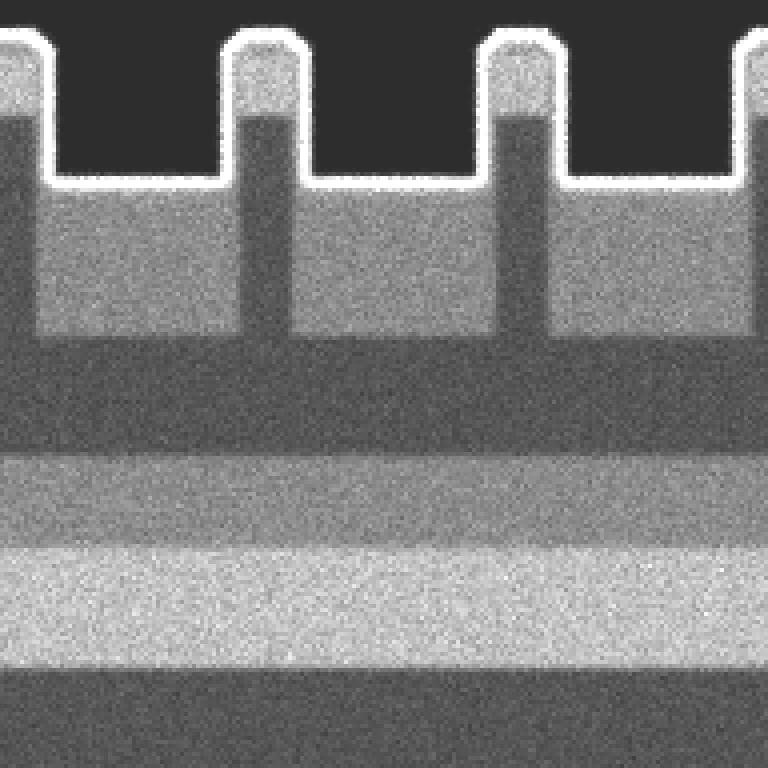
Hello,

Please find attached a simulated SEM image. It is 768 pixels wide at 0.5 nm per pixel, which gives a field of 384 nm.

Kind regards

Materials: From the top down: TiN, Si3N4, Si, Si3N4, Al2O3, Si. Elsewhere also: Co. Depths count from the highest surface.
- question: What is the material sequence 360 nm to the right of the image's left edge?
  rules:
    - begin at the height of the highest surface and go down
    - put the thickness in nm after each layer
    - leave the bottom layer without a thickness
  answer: empty 74, TiN 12, Si3N4 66, Si 60, Si3N4 46, Al2O3 60, Si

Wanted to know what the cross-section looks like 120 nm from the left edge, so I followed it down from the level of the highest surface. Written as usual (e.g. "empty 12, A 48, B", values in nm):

TiN 12, Co 30, Si 170, Si3N4 46, Al2O3 60, Si